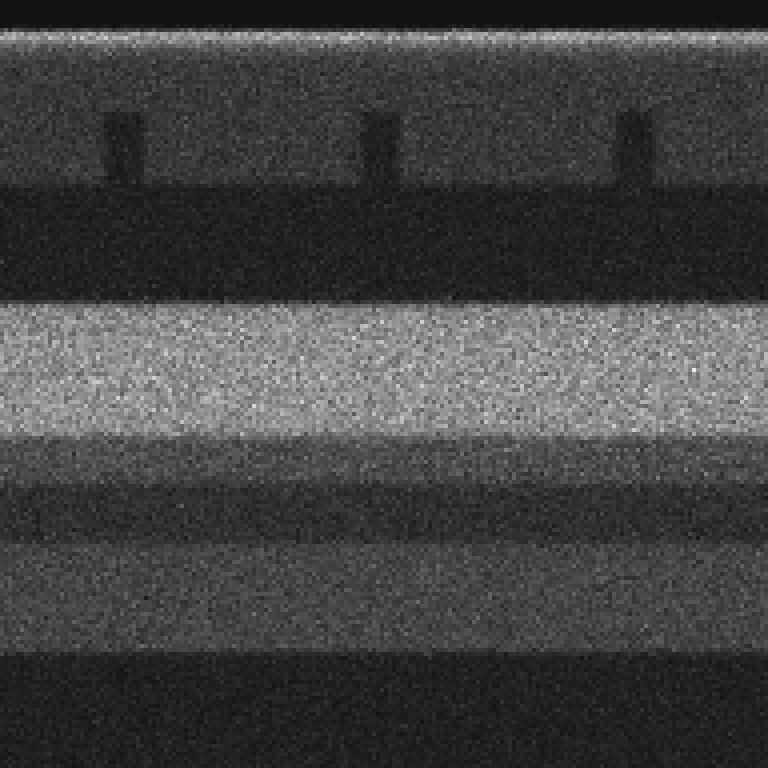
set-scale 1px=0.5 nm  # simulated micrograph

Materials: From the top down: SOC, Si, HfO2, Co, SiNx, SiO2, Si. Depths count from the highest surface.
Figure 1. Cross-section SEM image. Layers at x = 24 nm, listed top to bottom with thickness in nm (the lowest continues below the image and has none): SOC 76, Si 60, HfO2 66, Co 24, SiNx 30, SiO2 54, Si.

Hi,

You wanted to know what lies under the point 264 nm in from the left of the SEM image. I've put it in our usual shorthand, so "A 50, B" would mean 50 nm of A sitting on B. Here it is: SOC 76, Si 60, HfO2 66, Co 24, SiNx 30, SiO2 54, Si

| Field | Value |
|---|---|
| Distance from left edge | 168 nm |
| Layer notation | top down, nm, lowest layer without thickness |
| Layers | SOC 76, Si 60, HfO2 66, Co 24, SiNx 30, SiO2 54, Si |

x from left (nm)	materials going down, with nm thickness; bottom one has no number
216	SOC 76, Si 60, HfO2 66, Co 24, SiNx 30, SiO2 54, Si